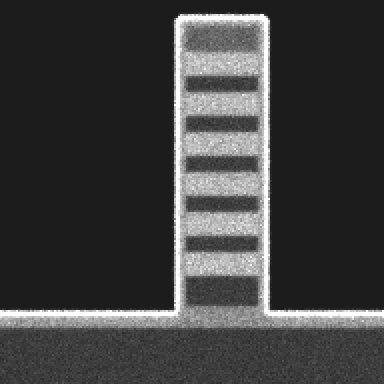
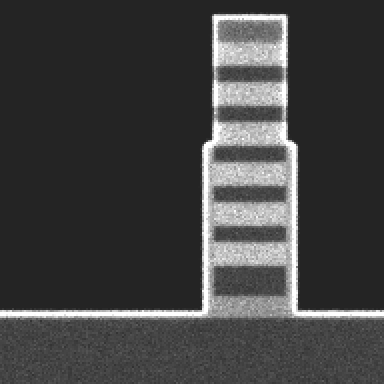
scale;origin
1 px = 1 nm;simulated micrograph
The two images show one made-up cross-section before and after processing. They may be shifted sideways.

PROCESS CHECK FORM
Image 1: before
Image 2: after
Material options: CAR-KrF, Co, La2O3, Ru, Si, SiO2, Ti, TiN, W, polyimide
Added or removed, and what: removed, Co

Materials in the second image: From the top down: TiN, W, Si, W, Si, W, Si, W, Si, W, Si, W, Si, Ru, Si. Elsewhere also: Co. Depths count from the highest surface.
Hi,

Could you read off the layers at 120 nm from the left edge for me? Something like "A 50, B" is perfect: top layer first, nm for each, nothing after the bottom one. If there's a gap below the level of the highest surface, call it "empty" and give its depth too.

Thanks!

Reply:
empty 296, Ru 6, Si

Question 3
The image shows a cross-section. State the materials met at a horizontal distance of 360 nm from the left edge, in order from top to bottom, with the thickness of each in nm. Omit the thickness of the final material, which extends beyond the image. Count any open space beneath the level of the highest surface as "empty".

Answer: empty 296, Ru 6, Si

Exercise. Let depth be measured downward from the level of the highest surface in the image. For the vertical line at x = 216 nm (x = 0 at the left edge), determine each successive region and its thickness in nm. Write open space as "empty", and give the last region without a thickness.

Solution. TiN 26, W 24, Si 16, W 24, Si 16, W 24, Si 16, W 24, Si 16, W 24, Si 16, W 24, Si 30, Ru 22, Si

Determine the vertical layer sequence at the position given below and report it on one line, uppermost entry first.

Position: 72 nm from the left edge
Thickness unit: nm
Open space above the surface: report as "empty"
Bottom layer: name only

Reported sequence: empty 296, Ru 6, Si